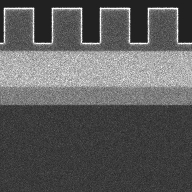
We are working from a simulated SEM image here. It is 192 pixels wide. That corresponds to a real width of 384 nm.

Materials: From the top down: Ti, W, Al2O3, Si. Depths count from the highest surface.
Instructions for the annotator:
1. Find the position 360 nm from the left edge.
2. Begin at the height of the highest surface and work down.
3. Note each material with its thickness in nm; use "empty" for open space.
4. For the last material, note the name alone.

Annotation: empty 70, Ti 16, W 72, Al2O3 36, Si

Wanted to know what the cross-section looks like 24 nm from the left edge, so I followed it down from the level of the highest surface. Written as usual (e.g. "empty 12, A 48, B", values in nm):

Ti 86, W 72, Al2O3 36, Si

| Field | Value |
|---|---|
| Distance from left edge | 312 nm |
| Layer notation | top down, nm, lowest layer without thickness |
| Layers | Ti 86, W 72, Al2O3 36, Si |